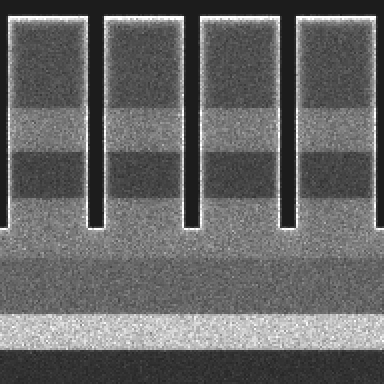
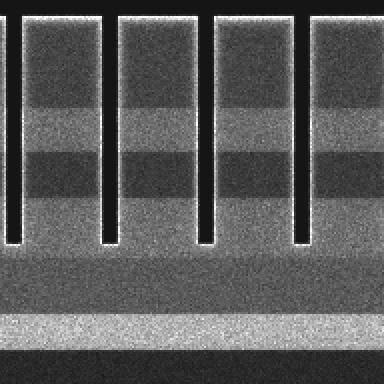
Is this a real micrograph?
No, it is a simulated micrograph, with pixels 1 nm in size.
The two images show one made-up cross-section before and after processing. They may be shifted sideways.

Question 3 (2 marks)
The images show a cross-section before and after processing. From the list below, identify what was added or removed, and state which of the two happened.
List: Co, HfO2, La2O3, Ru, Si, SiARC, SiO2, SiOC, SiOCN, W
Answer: Ru was removed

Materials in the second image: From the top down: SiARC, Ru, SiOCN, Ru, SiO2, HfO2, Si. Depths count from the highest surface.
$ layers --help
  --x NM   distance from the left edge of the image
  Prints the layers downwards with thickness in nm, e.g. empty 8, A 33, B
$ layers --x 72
SiARC 92, Ru 44, SiOCN 46, Ru 60, SiO2 56, HfO2 36, Si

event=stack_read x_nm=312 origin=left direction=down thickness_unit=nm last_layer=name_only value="SiARC 92, Ru 44, SiOCN 46, Ru 60, SiO2 56, HfO2 36, Si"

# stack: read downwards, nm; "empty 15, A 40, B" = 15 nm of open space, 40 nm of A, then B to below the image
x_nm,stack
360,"SiARC 92, Ru 44, SiOCN 46, Ru 60, SiO2 56, HfO2 36, Si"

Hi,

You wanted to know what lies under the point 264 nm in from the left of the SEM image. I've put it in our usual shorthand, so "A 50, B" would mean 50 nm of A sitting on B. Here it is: SiARC 92, Ru 44, SiOCN 46, Ru 60, SiO2 56, HfO2 36, Si